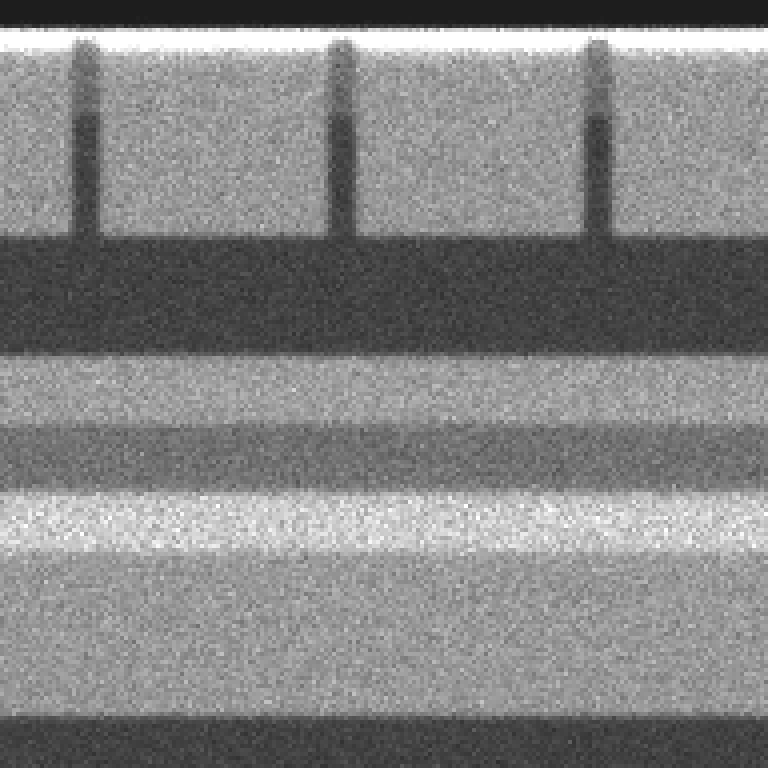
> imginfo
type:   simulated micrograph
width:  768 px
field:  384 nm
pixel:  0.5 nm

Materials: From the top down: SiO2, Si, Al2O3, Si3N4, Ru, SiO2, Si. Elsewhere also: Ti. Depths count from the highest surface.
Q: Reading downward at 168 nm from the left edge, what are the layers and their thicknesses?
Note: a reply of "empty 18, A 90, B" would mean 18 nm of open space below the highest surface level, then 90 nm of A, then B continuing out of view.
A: Ti 42, Si 120, Al2O3 34, Si3N4 34, Ru 30, SiO2 82, Si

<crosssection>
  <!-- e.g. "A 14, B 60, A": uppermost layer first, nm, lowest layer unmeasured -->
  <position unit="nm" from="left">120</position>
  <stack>SiO2 102, Si 60, Al2O3 34, Si3N4 34, Ru 30, SiO2 82, Si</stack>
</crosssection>